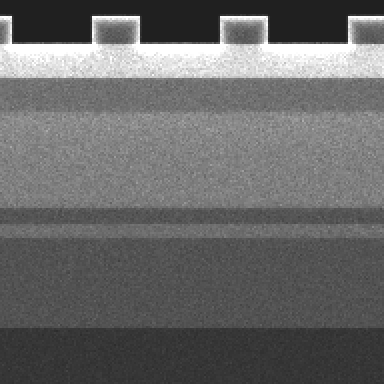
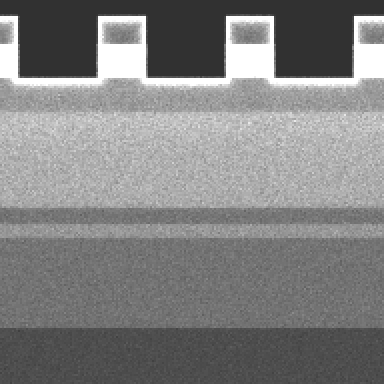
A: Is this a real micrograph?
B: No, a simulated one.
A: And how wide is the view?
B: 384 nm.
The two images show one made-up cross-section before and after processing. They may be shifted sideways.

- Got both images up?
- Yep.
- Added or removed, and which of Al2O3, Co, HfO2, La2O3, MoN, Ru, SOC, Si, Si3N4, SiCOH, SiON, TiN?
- removed, HfO2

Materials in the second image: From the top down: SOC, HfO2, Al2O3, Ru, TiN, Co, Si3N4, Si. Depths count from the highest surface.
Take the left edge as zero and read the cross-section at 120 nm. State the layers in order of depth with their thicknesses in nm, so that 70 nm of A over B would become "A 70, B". SOC 28, HfO2 34, Al2O3 34, Ru 96, TiN 16, Co 14, Si3N4 90, Si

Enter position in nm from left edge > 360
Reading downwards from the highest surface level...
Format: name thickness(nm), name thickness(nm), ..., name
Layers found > SOC 28, HfO2 34, Al2O3 34, Ru 96, TiN 16, Co 14, Si3N4 90, Si